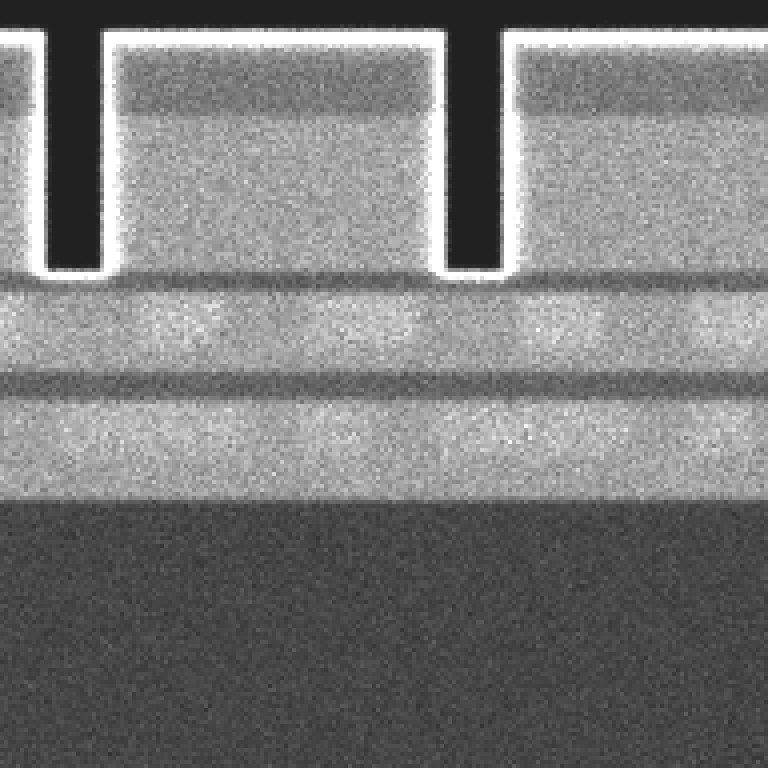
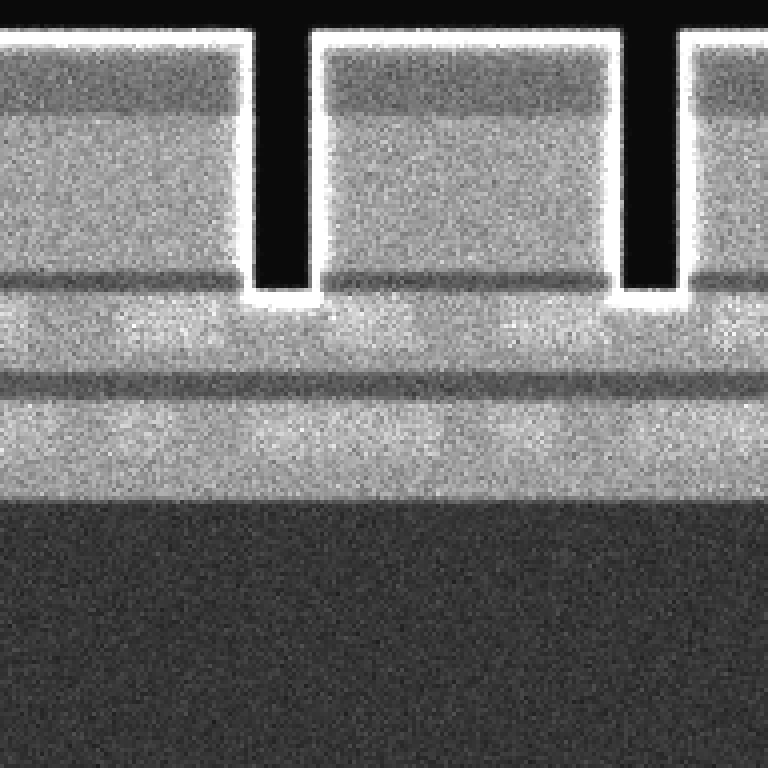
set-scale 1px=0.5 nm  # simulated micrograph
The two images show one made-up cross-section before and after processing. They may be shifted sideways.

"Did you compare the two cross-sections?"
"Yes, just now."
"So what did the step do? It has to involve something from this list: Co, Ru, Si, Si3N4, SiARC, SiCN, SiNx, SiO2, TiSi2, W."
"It removed SiCN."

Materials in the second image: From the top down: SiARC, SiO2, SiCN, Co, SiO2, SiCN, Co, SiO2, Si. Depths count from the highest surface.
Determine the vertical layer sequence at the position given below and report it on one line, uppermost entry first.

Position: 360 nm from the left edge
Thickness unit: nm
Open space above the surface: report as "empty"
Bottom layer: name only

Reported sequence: SiARC 42, SiO2 78, SiCN 10, Co 28, SiO2 12, SiCN 14, Co 28, SiO2 22, Si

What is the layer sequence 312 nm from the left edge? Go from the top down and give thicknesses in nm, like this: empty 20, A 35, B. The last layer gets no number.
empty 130, SiO2 40, SiCN 14, SiO2 50, Si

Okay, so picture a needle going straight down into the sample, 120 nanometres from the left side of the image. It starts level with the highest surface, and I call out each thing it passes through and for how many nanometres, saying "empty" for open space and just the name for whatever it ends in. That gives SiARC 42, SiO2 78, SiCN 10, SiO2 40, SiCN 14, SiO2 50, Si